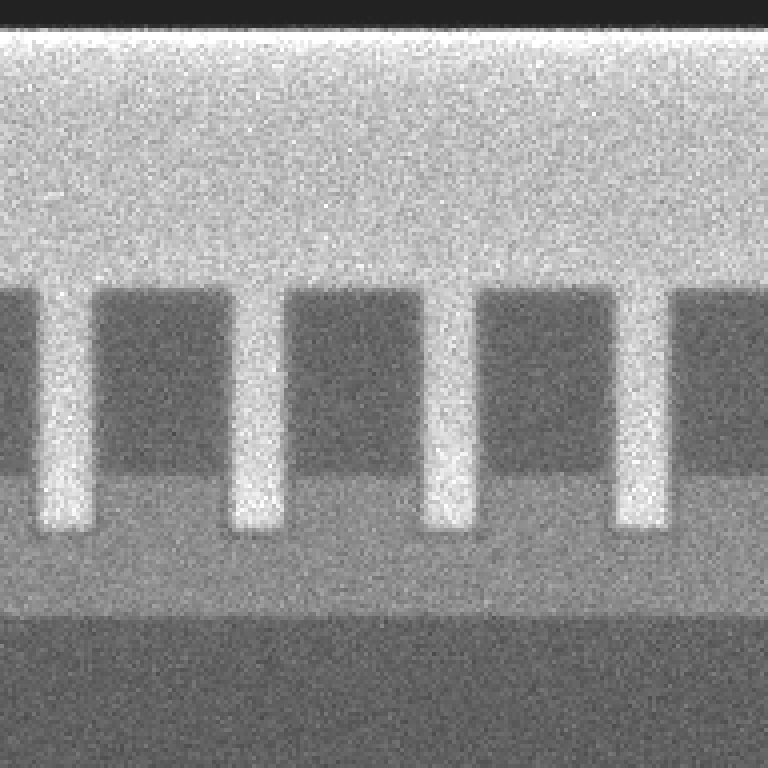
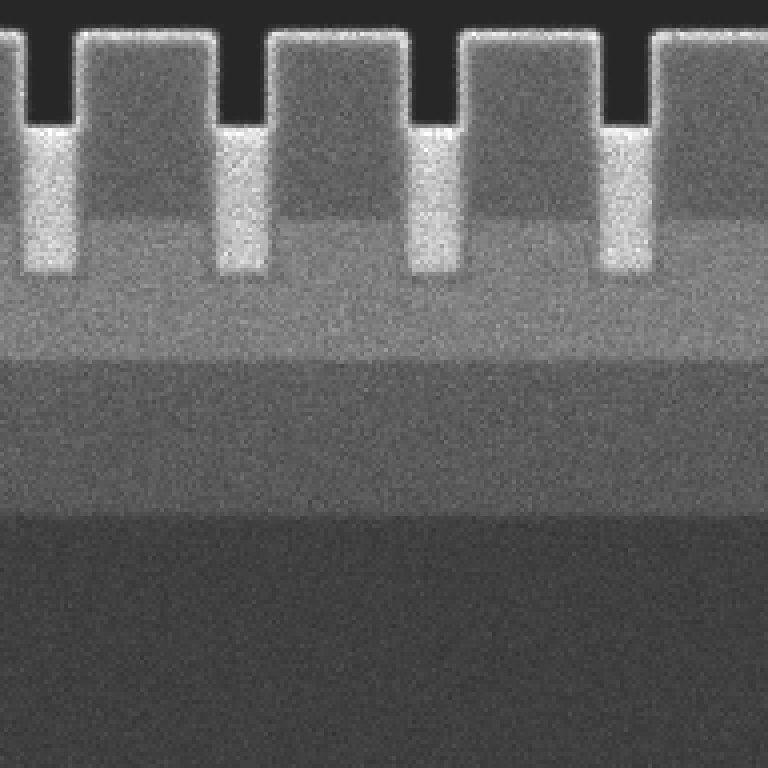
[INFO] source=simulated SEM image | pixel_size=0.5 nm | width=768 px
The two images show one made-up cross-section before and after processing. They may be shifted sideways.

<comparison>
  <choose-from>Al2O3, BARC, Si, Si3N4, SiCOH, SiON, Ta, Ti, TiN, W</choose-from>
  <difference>W removed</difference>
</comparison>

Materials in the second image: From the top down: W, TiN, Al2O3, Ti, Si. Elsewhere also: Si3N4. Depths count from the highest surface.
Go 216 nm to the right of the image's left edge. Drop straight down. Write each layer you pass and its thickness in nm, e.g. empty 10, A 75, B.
empty 48, W 72, TiN 6, Al2O3 38, Ti 78, Si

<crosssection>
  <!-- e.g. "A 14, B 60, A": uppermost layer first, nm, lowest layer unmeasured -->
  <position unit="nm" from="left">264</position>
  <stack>TiN 6, Si3N4 88, Al2O3 70, Ti 78, Si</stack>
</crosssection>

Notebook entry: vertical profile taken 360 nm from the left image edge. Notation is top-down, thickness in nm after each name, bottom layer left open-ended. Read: TiN 6, Si3N4 88, Al2O3 70, Ti 78, Si